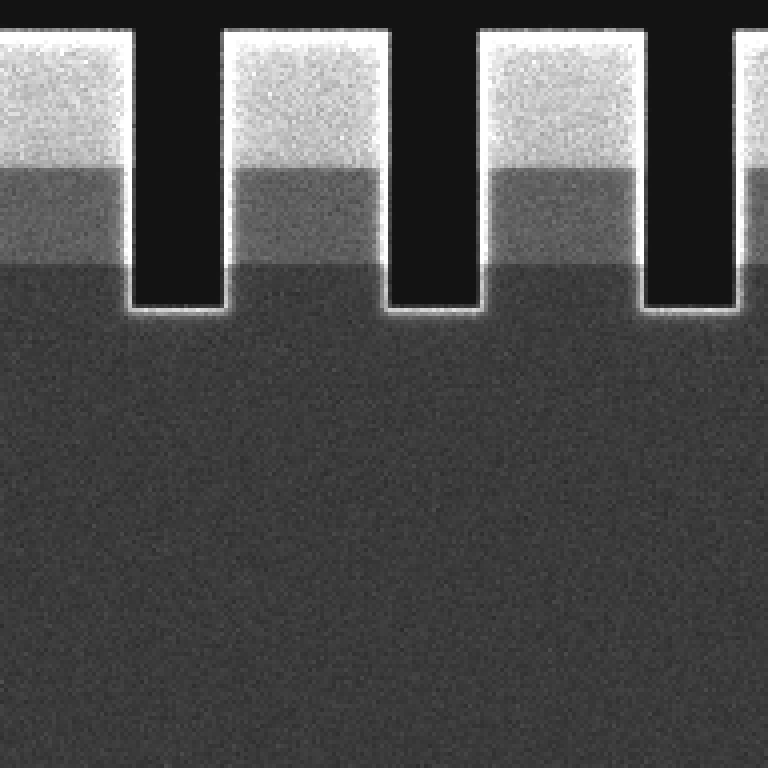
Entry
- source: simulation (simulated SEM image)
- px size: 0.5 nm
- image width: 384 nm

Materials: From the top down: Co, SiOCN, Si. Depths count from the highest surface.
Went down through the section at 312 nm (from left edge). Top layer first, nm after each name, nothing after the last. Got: Co 68, SiOCN 48, Si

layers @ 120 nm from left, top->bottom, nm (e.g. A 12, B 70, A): Co 68, SiOCN 48, Si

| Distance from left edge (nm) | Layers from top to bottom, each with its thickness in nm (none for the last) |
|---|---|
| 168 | Co 68, SiOCN 48, Si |